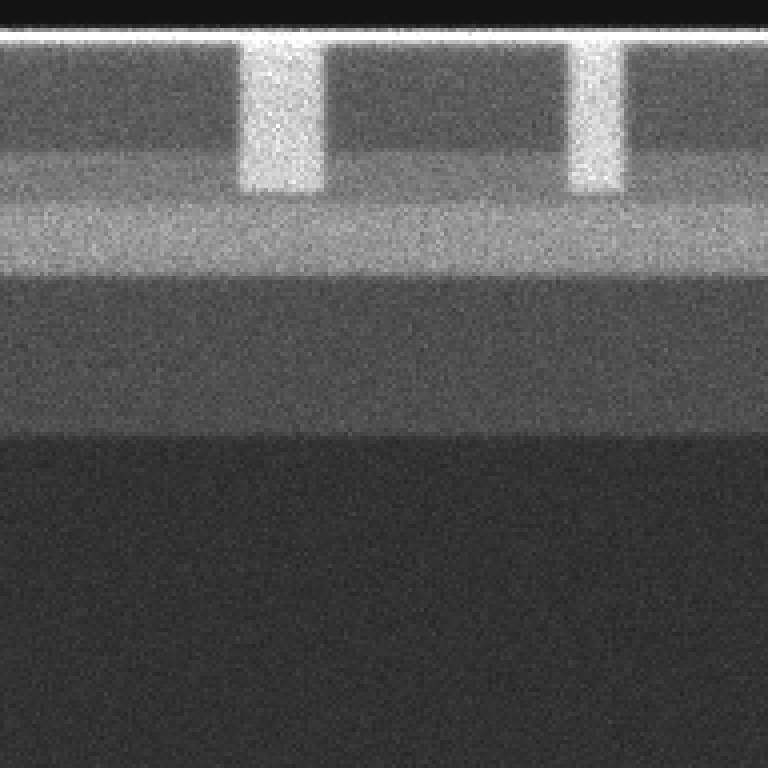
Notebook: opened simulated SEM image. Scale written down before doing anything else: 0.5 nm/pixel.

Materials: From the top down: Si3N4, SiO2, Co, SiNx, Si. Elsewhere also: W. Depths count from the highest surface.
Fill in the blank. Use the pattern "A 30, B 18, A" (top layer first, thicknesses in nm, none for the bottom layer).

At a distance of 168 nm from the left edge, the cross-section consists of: Si3N4 60, SiO2 26, Co 36, SiNx 80, Si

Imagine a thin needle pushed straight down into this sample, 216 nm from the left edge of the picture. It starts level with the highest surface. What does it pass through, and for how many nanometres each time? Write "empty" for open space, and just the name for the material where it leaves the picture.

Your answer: Si3N4 60, SiO2 26, Co 36, SiNx 80, Si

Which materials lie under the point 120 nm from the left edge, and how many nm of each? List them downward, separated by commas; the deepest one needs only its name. W 80, SiO2 6, Co 36, SiNx 80, Si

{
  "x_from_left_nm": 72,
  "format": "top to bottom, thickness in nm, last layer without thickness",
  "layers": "Si3N4 60, SiO2 26, Co 36, SiNx 80, Si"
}